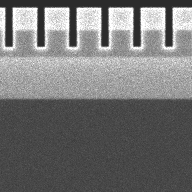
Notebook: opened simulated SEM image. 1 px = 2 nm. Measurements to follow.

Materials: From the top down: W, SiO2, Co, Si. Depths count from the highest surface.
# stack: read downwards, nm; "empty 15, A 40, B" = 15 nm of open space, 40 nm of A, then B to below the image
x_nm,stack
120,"W 44, SiO2 54, Co 84, Si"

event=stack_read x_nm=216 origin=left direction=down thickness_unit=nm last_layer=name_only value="empty 78, SiO2 20, Co 84, Si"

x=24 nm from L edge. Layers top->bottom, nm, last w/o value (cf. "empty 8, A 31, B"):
empty 78, SiO2 20, Co 84, Si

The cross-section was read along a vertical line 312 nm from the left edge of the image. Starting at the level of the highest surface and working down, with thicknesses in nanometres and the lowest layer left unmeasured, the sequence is W 44, SiO2 54, Co 84, Si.